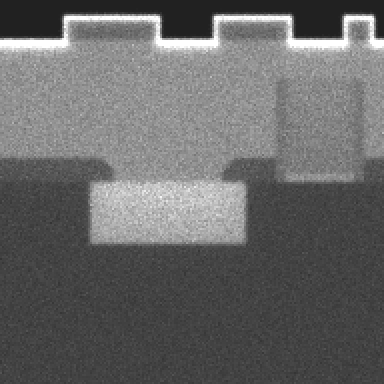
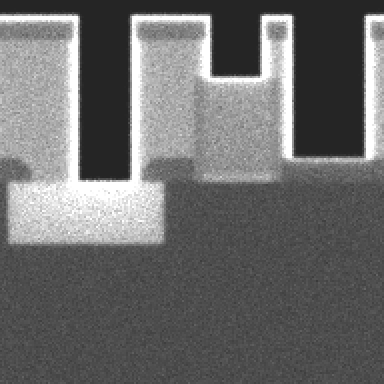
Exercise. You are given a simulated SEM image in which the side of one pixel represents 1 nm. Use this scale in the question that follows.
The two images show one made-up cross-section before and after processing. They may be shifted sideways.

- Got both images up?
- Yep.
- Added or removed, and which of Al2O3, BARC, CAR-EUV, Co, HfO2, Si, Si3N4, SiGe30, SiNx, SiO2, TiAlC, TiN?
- removed, SiO2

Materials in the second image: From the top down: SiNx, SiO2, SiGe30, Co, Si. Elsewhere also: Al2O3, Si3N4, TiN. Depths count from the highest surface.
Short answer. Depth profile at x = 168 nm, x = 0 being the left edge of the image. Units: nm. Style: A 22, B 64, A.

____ SiNx 24, SiO2 118, SiGe30 24, Si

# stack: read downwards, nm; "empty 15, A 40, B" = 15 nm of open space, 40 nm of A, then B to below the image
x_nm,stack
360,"empty 142, SiGe30 24, Si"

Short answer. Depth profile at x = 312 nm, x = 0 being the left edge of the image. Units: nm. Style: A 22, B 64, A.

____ empty 142, SiGe30 24, Si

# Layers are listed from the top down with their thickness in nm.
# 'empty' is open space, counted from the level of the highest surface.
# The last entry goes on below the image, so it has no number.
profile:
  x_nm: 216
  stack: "empty 62, TiN 96, Al2O3 8, Si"